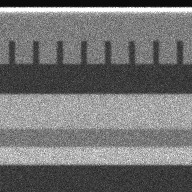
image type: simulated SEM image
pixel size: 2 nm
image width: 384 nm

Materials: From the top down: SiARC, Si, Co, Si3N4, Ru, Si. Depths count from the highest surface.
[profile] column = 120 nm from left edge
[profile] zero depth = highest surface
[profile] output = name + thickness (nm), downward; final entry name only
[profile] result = SiARC 66, Si 106, Co 70, Si3N4 36, Ru 36, Si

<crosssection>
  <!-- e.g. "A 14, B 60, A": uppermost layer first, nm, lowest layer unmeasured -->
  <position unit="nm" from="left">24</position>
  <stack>SiARC 66, Si 106, Co 70, Si3N4 36, Ru 36, Si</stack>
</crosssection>